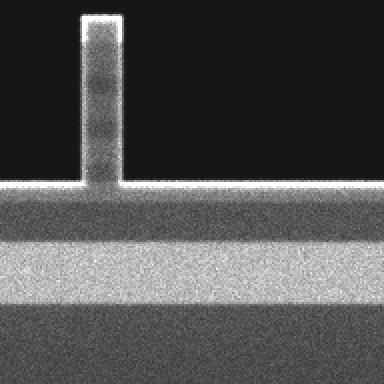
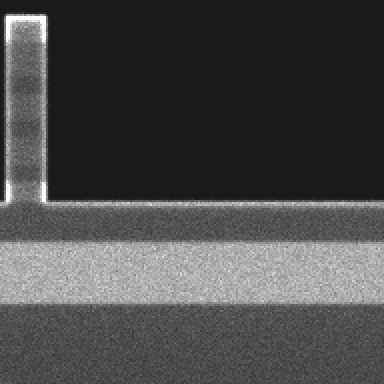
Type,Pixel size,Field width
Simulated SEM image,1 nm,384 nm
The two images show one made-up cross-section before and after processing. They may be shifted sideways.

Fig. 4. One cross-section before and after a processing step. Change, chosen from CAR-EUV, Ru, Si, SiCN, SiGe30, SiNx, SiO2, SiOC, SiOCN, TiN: SiOCN removed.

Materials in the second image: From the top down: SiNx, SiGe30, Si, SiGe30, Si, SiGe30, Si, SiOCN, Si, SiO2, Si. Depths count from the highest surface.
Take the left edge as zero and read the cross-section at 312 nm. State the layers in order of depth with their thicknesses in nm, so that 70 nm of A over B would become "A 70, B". empty 186, Si 40, SiO2 62, Si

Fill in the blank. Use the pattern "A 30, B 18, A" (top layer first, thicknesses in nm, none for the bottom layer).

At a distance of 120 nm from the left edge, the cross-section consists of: empty 186, Si 40, SiO2 62, Si